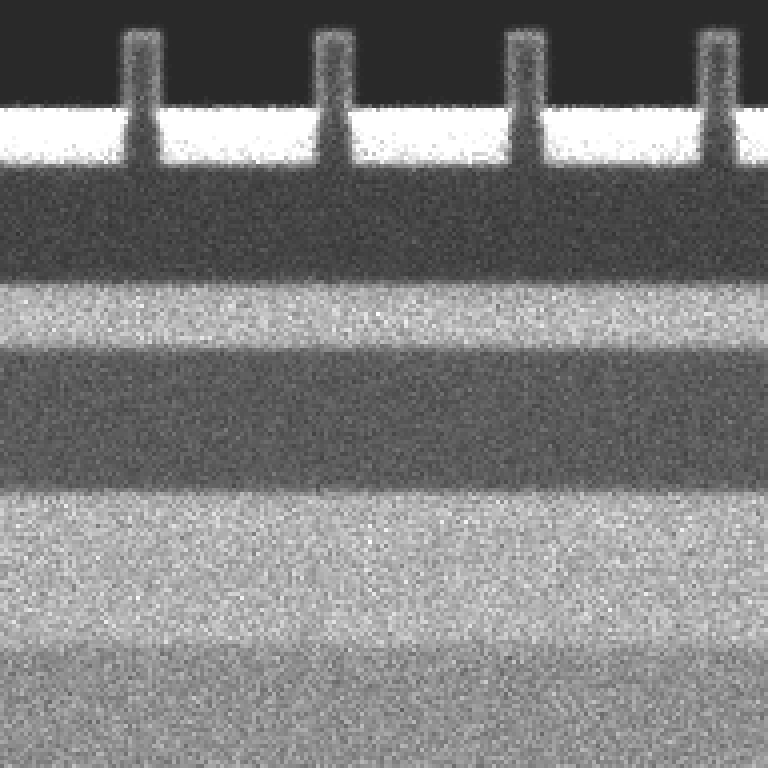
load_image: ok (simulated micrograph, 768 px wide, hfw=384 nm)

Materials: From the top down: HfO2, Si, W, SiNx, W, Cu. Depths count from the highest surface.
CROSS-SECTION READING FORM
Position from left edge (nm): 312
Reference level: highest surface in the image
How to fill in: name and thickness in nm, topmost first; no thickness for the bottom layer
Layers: empty 40, HfO2 26, Si 60, W 32, SiNx 72, W 76, Cu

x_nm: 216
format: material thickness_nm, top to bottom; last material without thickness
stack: empty 40, HfO2 26, Si 60, W 32, SiNx 72, W 76, Cu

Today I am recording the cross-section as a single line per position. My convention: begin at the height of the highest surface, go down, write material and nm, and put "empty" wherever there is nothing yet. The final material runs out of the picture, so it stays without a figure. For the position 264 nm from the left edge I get Si 126, W 32, SiNx 72, W 76, Cu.